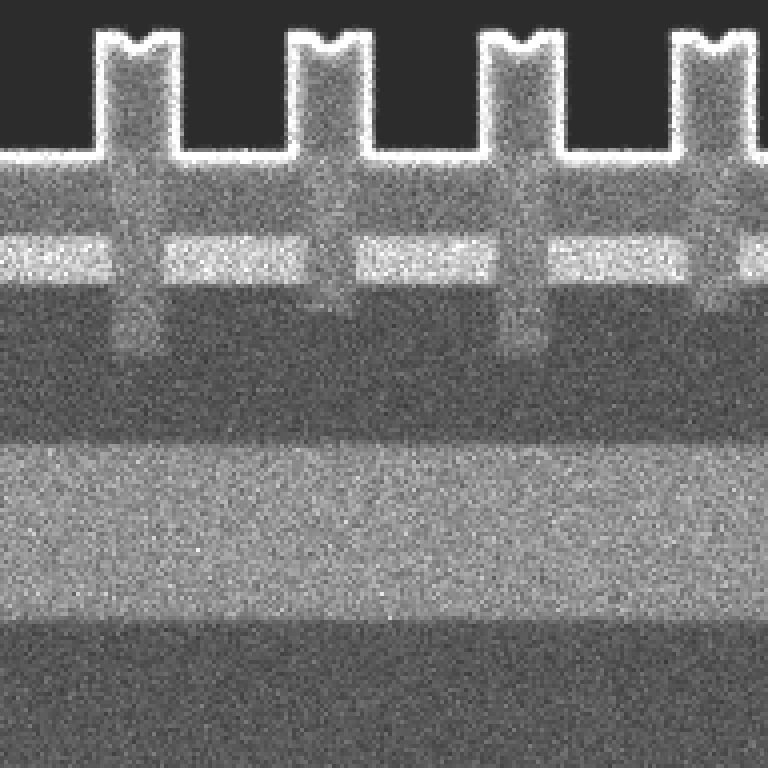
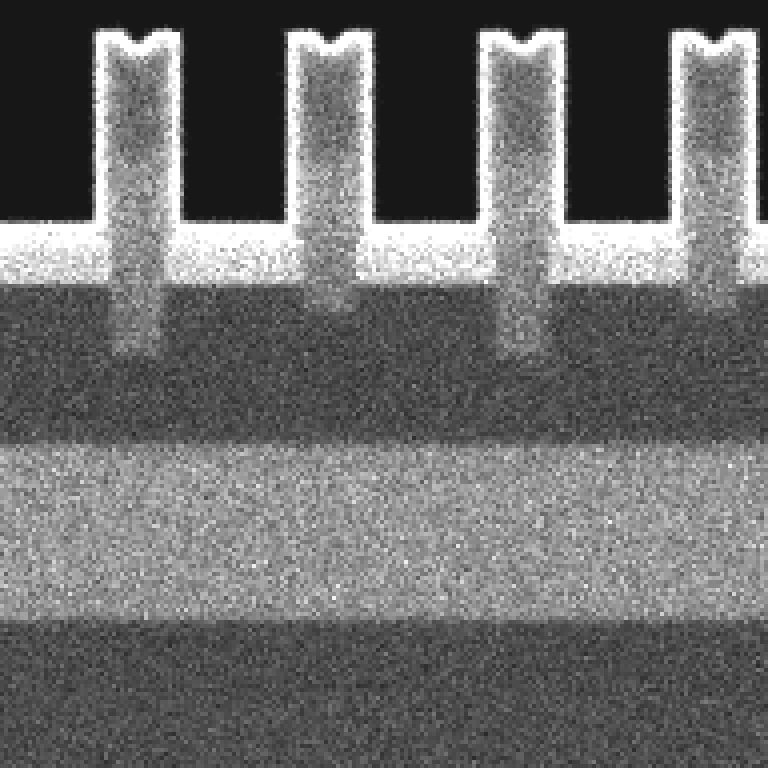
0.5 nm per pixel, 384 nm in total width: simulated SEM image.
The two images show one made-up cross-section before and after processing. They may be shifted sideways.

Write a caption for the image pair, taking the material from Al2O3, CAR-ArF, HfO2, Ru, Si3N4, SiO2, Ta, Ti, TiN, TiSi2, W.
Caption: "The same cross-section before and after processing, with Al2O3 removed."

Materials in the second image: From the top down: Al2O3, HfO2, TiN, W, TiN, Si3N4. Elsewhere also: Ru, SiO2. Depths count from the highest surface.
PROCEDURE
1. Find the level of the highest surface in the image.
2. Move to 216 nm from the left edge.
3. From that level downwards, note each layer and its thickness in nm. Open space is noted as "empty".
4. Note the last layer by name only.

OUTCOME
empty 96, Al2O3 6, HfO2 24, TiN 80, W 88, TiN 36, Si3N4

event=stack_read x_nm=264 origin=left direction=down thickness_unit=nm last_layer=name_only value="empty 4, SiO2 56, Ru 102, TiN 44, W 88, TiN 36, Si3N4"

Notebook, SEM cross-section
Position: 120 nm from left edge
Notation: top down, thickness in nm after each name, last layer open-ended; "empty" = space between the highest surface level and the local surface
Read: empty 96, Al2O3 6, HfO2 24, TiN 80, W 88, TiN 36, Si3N4